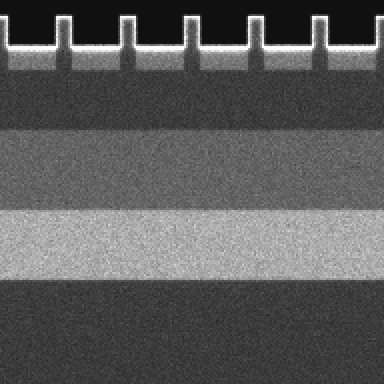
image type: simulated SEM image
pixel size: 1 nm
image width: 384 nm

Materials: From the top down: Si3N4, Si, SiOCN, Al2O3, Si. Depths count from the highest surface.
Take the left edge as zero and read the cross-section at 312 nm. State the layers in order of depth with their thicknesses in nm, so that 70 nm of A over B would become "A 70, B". Si 114, SiOCN 80, Al2O3 70, Si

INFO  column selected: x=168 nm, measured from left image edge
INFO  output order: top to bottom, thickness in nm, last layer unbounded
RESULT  empty 30, Si3N4 24, Si 60, SiOCN 80, Al2O3 70, Si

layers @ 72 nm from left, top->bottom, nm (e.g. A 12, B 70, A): empty 30, Si3N4 24, Si 60, SiOCN 80, Al2O3 70, Si